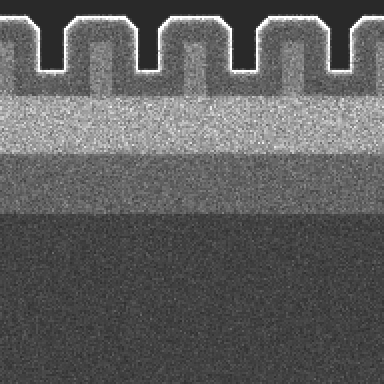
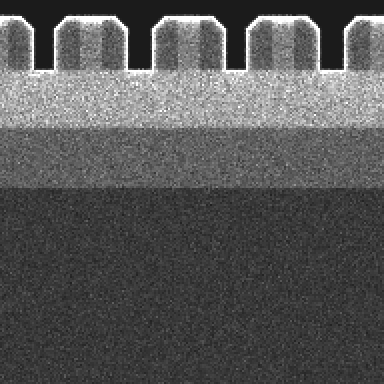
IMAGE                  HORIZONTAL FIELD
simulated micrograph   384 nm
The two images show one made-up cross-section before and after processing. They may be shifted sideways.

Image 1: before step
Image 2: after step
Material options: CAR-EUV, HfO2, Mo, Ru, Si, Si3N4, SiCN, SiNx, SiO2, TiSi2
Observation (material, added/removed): SiNx, removed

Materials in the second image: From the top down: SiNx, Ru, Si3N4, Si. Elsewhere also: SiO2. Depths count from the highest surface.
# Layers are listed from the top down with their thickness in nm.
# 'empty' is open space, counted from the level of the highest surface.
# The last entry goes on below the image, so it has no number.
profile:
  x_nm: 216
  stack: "empty 4, SiNx 50, Ru 58, Si3N4 60, Si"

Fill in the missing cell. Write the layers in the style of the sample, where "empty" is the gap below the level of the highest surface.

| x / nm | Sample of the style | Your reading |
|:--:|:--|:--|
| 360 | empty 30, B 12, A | SiNx 54, Ru 58, Si3N4 60, Si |